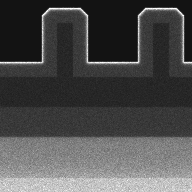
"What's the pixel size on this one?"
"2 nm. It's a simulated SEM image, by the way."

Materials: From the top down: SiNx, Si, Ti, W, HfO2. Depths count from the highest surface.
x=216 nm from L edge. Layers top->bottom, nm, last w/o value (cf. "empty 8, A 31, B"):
empty 108, SiNx 30, Si 60, Ti 60, W 82, HfO2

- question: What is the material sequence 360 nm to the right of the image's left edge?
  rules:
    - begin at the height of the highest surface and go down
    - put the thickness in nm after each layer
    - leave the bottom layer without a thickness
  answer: empty 8, SiNx 130, Si 60, Ti 60, W 82, HfO2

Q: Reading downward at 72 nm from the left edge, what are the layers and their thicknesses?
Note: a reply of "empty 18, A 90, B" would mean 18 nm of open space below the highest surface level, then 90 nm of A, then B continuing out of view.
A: empty 108, SiNx 30, Si 60, Ti 60, W 82, HfO2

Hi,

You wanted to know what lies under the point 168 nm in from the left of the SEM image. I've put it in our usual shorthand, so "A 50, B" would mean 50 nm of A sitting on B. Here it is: empty 8, SiNx 130, Si 60, Ti 60, W 82, HfO2